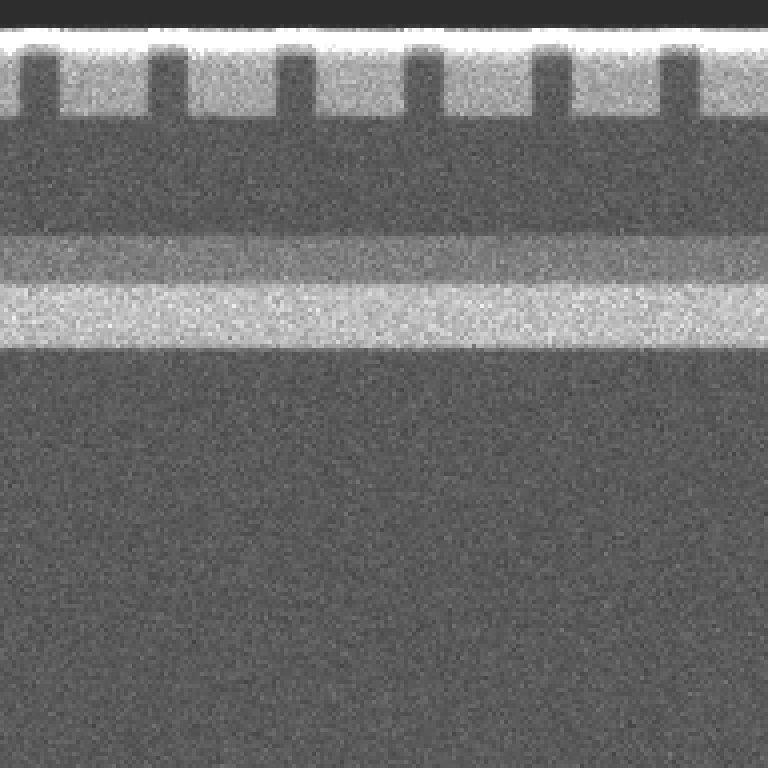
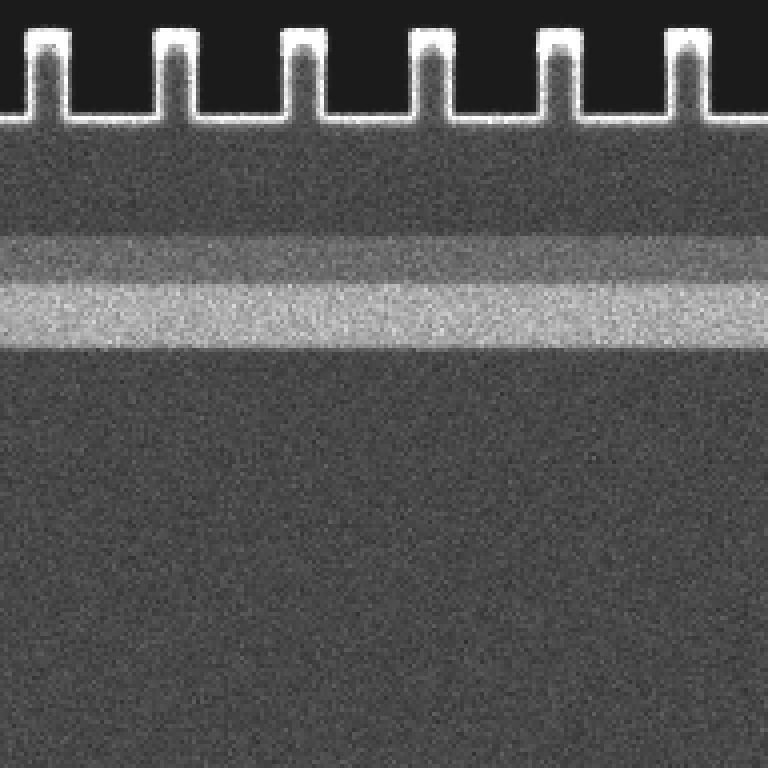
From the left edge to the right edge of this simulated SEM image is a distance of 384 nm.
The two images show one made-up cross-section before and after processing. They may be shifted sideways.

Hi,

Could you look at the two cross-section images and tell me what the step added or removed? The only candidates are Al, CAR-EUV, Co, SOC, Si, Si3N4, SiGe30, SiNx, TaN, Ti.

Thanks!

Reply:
removed SOC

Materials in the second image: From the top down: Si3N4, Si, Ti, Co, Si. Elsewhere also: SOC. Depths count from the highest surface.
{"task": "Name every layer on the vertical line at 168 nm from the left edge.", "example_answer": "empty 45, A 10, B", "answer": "empty 42, Si 60, Ti 24, Co 32, Si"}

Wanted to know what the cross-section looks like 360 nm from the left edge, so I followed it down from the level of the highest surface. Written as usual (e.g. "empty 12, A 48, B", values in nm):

empty 42, Si 60, Ti 24, Co 32, Si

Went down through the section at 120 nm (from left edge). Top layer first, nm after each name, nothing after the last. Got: empty 42, Si 60, Ti 24, Co 32, Si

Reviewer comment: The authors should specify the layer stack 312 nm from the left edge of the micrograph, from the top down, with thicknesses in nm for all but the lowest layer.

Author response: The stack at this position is empty 42, Si 60, Ti 24, Co 32, Si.